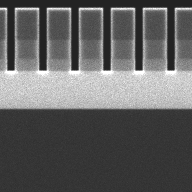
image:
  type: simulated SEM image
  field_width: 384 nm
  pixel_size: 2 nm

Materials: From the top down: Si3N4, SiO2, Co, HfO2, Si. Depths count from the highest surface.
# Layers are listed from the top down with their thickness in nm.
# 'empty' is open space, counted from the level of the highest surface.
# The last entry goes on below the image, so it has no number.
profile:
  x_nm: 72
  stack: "Si3N4 64, SiO2 38, Co 24, HfO2 76, Si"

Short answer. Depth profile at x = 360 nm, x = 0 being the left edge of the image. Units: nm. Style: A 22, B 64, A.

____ Si3N4 64, SiO2 38, Co 24, HfO2 76, Si